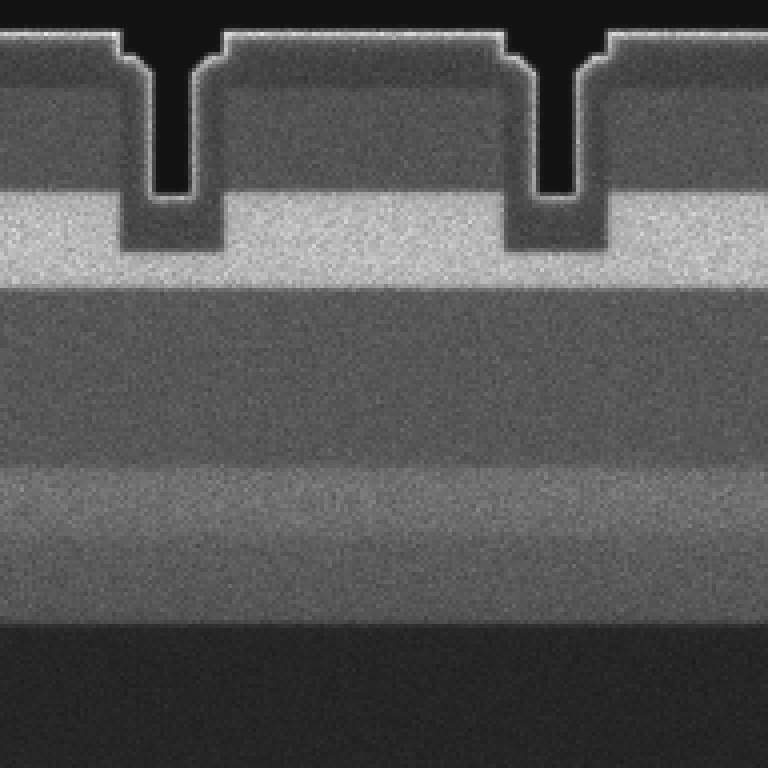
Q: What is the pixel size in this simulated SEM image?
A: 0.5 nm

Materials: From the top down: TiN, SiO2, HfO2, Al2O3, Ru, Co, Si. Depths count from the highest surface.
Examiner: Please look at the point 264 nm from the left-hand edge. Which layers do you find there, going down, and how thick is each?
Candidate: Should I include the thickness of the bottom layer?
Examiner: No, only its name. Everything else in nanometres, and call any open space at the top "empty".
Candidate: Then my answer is empty 18, TiN 92, HfO2 18, Al2O3 90, Ru 34, Co 44, Si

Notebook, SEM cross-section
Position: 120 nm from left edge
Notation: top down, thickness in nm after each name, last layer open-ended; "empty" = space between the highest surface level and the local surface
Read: TiN 28, SiO2 52, HfO2 48, Al2O3 90, Ru 34, Co 44, Si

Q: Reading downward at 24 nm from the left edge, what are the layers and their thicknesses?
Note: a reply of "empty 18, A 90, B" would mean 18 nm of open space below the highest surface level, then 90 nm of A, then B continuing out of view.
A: TiN 28, SiO2 52, HfO2 48, Al2O3 90, Ru 34, Co 44, Si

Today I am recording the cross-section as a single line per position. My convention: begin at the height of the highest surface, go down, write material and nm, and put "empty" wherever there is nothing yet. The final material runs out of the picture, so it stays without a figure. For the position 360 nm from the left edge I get TiN 28, SiO2 52, HfO2 48, Al2O3 90, Ru 34, Co 44, Si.